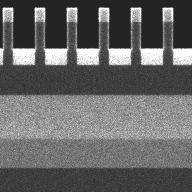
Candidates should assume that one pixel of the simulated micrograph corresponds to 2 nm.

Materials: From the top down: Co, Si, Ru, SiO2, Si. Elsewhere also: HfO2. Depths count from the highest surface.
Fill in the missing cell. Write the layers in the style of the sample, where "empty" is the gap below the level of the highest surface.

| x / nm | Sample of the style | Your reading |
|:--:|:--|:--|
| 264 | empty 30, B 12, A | Co 28, Si 146, Ru 88, SiO2 58, Si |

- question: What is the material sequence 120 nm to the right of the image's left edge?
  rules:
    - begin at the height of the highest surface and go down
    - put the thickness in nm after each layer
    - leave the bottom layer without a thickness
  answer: empty 82, HfO2 32, Si 60, Ru 88, SiO2 58, Si